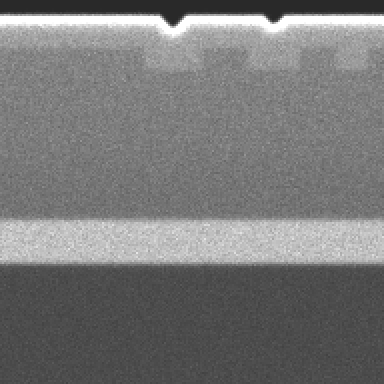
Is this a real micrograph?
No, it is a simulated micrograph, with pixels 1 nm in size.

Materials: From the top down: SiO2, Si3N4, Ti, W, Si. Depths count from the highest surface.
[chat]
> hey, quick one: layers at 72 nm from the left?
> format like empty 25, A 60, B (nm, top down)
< SiO2 32, Si3N4 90, Ti 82, W 44, Si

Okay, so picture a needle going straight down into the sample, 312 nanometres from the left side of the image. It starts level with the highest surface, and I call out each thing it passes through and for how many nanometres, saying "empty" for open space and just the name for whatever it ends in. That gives SiO2 32, Si3N4 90, Ti 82, W 44, Si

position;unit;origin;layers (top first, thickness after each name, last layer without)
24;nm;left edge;SiO2 32, Si3N4 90, Ti 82, W 44, Si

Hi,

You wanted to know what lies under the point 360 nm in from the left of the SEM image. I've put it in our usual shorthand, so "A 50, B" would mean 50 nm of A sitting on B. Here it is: SiO2 54, Si3N4 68, Ti 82, W 44, Si